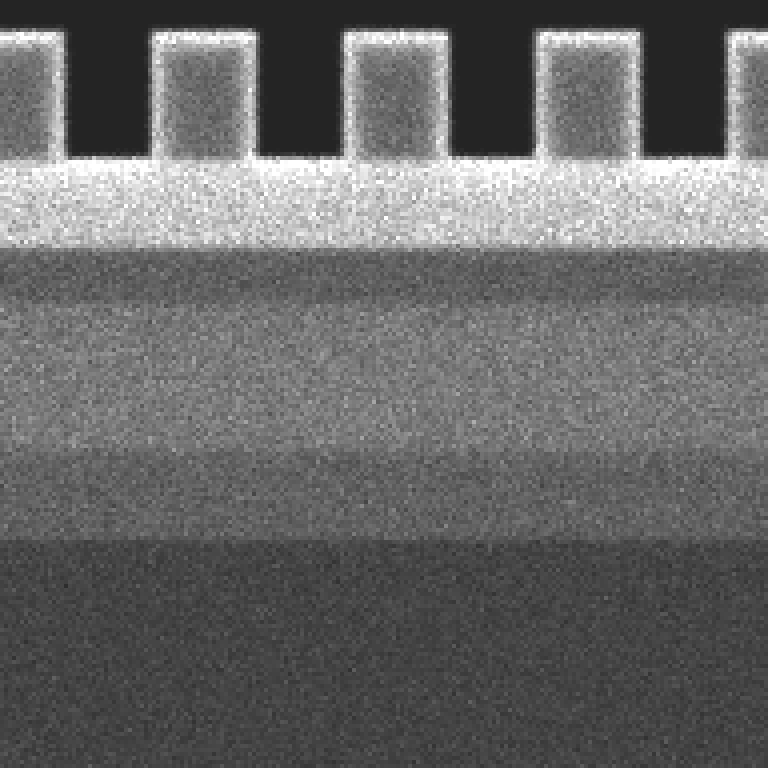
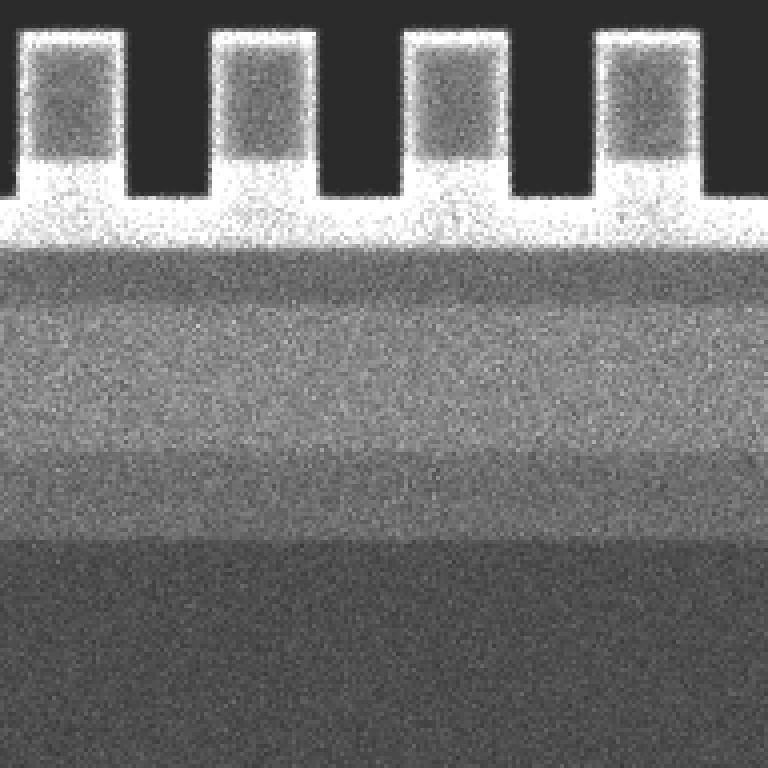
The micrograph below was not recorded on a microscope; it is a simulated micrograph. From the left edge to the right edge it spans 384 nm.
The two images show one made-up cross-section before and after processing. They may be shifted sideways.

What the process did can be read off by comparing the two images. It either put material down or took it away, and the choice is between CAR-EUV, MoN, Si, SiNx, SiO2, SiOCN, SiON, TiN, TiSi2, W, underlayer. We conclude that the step removed W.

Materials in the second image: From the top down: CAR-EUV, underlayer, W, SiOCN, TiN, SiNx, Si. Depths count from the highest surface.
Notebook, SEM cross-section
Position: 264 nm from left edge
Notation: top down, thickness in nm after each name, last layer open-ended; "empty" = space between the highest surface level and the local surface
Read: empty 84, W 24, SiOCN 28, TiN 74, SiNx 44, Si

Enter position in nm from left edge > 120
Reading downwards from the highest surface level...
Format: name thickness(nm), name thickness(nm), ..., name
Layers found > CAR-EUV 46, underlayer 18, W 44, SiOCN 28, TiN 74, SiNx 44, Si